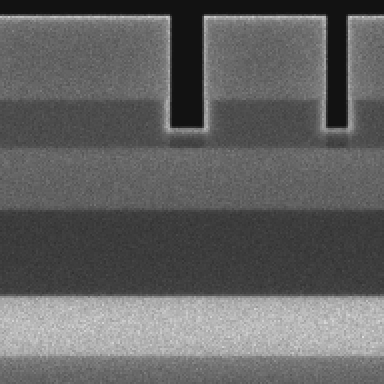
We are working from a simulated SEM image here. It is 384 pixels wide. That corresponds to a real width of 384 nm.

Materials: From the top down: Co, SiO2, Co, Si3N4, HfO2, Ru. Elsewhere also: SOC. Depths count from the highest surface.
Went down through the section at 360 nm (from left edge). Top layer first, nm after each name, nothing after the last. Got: Co 84, SiO2 48, Co 62, Si3N4 86, HfO2 60, Ru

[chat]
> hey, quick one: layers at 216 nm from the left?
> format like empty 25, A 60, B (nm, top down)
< Co 84, SiO2 48, Co 62, Si3N4 86, HfO2 60, Ru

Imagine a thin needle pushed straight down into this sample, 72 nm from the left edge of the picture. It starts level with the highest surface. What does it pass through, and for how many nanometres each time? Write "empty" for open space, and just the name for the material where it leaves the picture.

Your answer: Co 84, SiO2 48, Co 62, Si3N4 86, HfO2 60, Ru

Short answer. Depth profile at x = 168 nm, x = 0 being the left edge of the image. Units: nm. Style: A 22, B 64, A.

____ Co 84, SiO2 48, Co 62, Si3N4 86, HfO2 60, Ru